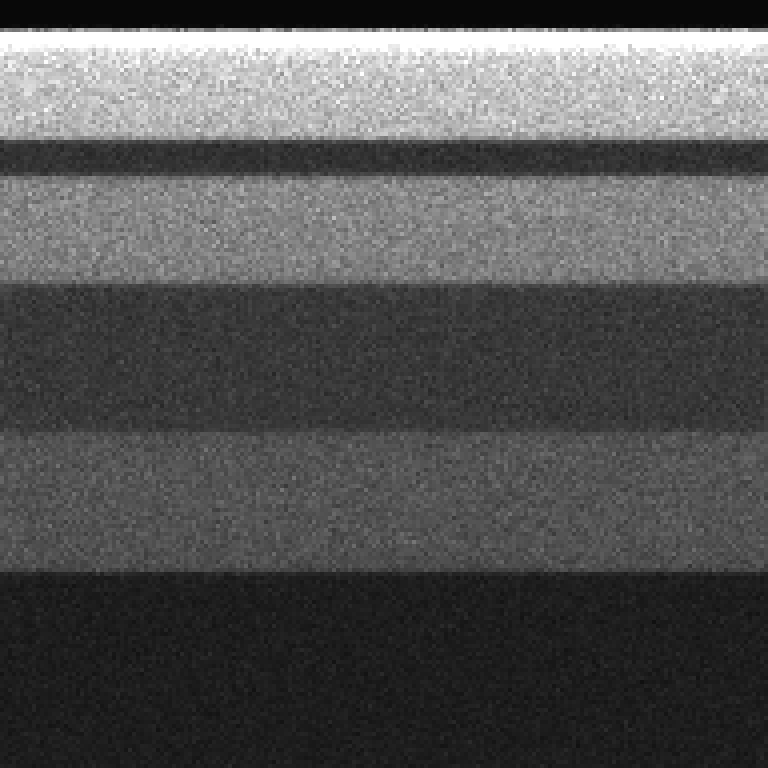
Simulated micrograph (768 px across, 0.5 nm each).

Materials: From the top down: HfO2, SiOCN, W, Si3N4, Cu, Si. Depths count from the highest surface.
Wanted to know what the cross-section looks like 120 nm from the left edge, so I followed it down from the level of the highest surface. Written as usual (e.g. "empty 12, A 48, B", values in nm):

HfO2 54, SiOCN 18, W 54, Si3N4 74, Cu 70, Si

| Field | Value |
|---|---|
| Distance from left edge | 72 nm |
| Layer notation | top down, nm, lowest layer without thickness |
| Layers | HfO2 54, SiOCN 18, W 54, Si3N4 74, Cu 70, Si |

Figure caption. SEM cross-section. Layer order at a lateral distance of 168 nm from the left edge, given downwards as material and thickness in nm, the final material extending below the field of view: HfO2 54, SiOCN 18, W 54, Si3N4 74, Cu 70, Si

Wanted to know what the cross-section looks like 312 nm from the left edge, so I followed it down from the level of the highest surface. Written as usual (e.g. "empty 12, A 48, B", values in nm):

HfO2 54, SiOCN 18, W 54, Si3N4 74, Cu 70, Si